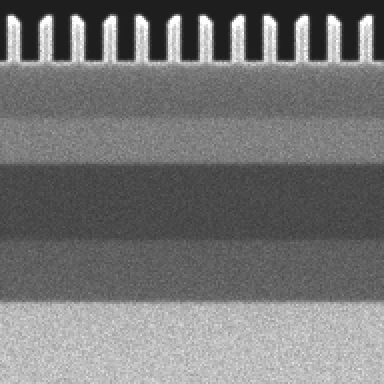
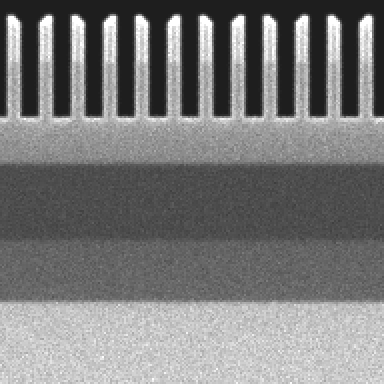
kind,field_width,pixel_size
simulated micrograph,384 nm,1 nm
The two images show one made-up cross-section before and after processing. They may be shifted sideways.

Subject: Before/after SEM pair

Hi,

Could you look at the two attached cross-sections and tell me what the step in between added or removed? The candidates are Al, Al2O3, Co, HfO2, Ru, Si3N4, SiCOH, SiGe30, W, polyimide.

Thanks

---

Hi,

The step removed Ru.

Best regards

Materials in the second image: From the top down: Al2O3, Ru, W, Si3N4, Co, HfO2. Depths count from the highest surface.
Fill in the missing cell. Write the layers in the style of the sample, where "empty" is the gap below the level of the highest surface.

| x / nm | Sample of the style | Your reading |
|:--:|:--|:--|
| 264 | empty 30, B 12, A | Al2O3 46, Ru 56, W 46, Si3N4 76, Co 62, HfO2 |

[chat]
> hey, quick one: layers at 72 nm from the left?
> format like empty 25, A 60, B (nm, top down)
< Al2O3 46, Ru 56, W 46, Si3N4 76, Co 62, HfO2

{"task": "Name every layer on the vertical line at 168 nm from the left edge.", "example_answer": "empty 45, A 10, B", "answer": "empty 6, Al2O3 40, Ru 56, W 46, Si3N4 76, Co 62, HfO2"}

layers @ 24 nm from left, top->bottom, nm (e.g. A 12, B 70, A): empty 102, W 46, Si3N4 76, Co 62, HfO2